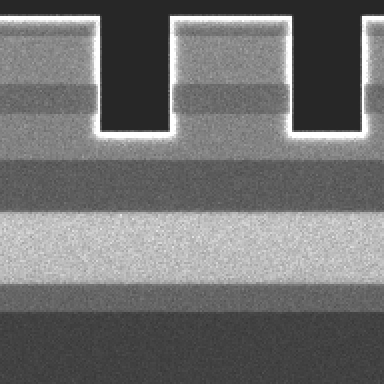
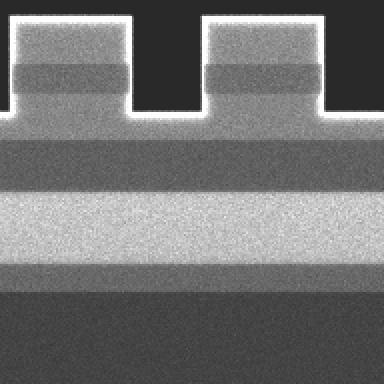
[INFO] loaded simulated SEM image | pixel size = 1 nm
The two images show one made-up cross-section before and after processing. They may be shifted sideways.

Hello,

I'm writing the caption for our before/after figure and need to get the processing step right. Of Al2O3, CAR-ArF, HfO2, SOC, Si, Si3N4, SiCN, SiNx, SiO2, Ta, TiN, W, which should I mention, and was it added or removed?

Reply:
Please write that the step removed SOC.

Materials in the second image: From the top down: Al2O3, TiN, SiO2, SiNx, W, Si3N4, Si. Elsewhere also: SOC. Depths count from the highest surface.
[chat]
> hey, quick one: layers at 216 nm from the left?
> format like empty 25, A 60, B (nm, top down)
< Al2O3 48, TiN 30, SiO2 46, SiNx 52, W 72, Si3N4 28, Si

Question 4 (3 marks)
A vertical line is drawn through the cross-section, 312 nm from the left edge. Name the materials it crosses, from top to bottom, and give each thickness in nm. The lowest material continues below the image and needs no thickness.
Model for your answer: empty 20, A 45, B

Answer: Al2O3 48, TiN 30, SiO2 46, SiNx 52, W 72, Si3N4 28, Si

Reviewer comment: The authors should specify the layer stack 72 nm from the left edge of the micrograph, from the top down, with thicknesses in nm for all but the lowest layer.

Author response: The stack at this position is Al2O3 48, TiN 30, SiO2 46, SiNx 52, W 72, Si3N4 28, Si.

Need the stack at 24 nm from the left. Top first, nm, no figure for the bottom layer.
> Al2O3 48, TiN 30, SiO2 46, SiNx 52, W 72, Si3N4 28, Si